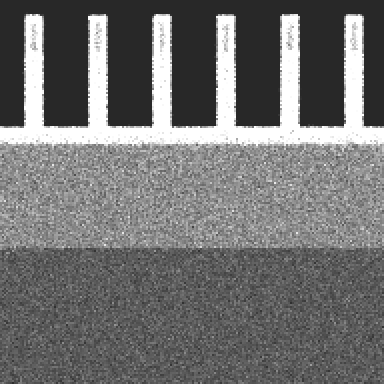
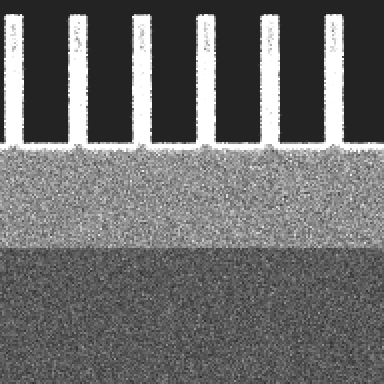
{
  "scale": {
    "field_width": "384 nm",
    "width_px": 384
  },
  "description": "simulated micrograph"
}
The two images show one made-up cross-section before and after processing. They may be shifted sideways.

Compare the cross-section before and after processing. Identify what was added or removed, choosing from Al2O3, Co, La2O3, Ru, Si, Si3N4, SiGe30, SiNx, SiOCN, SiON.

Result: Ru removed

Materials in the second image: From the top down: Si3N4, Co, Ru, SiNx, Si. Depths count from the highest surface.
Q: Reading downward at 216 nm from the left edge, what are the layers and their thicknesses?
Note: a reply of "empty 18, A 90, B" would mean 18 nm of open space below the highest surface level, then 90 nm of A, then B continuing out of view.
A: empty 128, SiNx 104, Si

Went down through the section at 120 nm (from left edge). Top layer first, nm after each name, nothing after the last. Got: empty 128, SiNx 104, Si